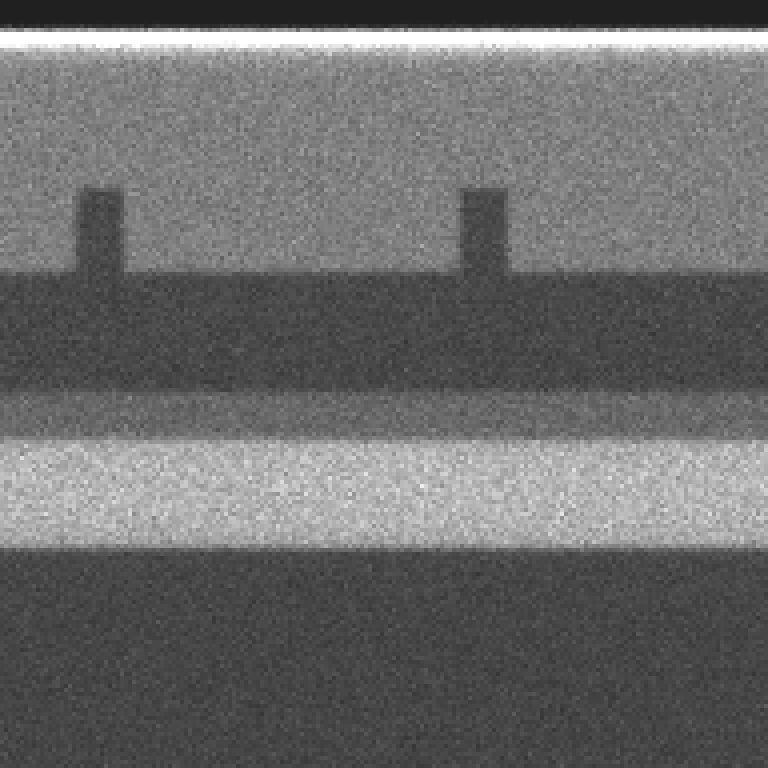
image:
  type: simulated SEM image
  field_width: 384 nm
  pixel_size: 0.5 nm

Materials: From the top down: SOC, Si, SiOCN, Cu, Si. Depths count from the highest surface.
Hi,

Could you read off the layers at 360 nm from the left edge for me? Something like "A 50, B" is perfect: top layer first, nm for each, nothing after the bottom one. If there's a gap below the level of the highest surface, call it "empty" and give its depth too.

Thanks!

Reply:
SOC 120, Si 60, SiOCN 24, Cu 54, Si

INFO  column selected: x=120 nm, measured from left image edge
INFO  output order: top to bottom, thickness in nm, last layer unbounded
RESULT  SOC 120, Si 60, SiOCN 24, Cu 54, Si